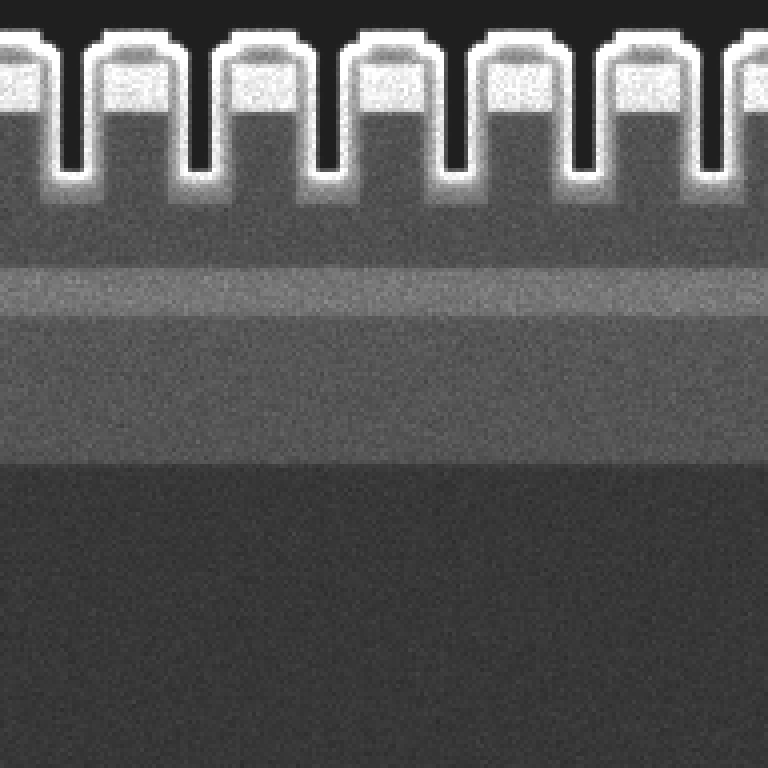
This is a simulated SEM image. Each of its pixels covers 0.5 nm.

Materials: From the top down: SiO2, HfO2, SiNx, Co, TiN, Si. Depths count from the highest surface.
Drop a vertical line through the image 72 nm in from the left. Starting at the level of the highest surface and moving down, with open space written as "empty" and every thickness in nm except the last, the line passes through SiO2 16, HfO2 24, SiNx 78, Co 24, TiN 74, Si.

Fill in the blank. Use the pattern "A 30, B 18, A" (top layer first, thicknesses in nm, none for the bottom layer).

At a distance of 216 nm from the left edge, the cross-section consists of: empty 6, SiO2 80, SiNx 32, Co 24, TiN 74, Si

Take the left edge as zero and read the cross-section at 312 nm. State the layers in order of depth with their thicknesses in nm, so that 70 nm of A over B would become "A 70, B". SiO2 16, HfO2 24, SiNx 78, Co 24, TiN 74, Si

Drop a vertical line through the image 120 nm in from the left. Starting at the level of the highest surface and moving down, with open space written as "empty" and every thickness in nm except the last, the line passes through SiO2 16, HfO2 24, SiNx 78, Co 24, TiN 74, Si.